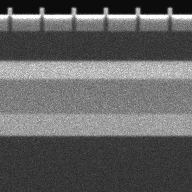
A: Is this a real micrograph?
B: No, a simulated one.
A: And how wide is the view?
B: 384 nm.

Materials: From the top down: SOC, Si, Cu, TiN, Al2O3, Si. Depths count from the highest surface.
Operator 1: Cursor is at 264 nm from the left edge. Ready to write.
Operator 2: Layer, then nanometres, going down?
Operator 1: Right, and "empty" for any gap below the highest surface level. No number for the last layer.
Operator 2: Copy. empty 14, SOC 32, Si 60, Cu 36, TiN 70, Al2O3 44, Si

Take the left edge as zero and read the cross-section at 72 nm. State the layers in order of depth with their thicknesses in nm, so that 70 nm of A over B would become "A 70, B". empty 14, SOC 32, Si 60, Cu 36, TiN 70, Al2O3 44, Si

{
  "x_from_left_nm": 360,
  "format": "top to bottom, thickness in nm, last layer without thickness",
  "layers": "empty 14, SOC 32, Si 60, Cu 36, TiN 70, Al2O3 44, Si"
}